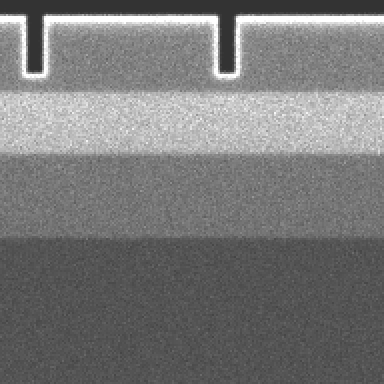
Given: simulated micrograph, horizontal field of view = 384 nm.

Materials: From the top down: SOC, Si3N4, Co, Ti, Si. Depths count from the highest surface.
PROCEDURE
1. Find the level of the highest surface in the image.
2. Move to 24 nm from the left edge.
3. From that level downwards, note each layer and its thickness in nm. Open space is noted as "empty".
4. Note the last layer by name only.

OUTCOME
SOC 14, Si3N4 62, Co 62, Ti 84, Si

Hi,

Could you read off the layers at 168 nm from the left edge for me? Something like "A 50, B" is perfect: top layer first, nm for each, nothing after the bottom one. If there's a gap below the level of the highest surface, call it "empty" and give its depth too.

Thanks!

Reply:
SOC 14, Si3N4 62, Co 62, Ti 84, Si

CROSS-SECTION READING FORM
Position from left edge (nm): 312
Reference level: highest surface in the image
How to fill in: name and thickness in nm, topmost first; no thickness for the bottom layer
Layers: SOC 14, Si3N4 62, Co 62, Ti 84, Si